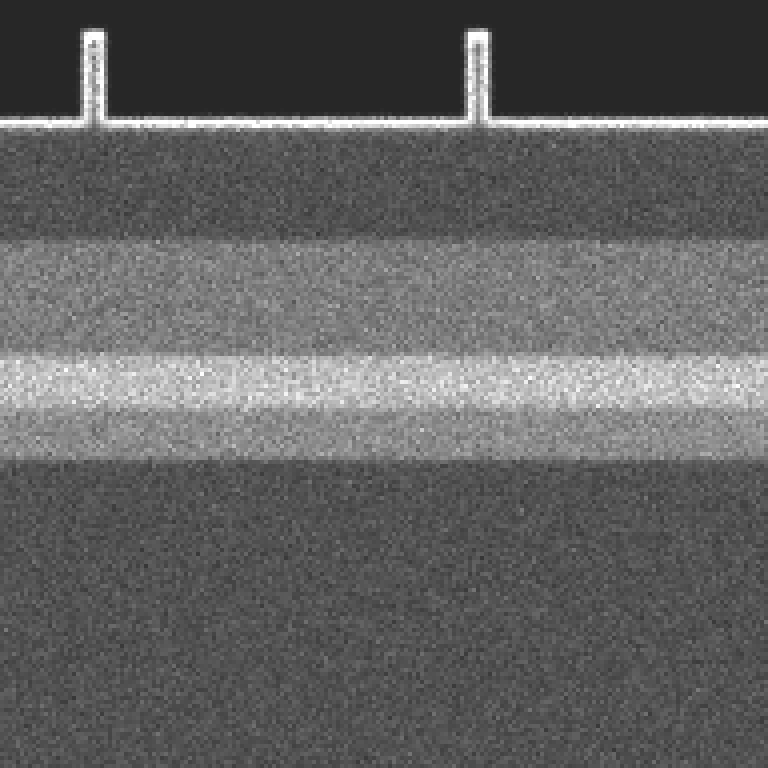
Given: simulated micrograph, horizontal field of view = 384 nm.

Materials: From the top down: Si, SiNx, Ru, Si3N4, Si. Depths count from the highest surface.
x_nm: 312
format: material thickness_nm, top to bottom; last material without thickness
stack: empty 44, Si 60, SiNx 58, Ru 26, Si3N4 26, Si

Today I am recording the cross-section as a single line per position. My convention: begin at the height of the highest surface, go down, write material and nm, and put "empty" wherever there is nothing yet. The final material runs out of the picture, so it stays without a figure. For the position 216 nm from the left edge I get empty 44, Si 60, SiNx 58, Ru 26, Si3N4 26, Si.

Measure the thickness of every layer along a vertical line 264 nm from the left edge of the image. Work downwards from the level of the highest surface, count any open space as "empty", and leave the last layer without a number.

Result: empty 44, Si 60, SiNx 58, Ru 26, Si3N4 26, Si